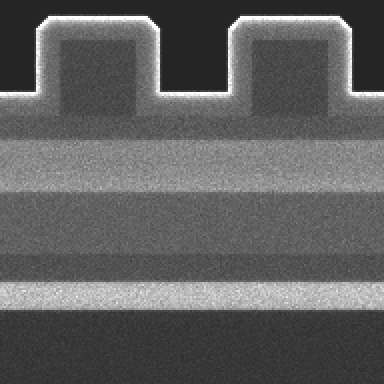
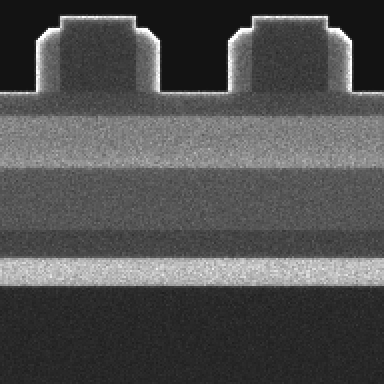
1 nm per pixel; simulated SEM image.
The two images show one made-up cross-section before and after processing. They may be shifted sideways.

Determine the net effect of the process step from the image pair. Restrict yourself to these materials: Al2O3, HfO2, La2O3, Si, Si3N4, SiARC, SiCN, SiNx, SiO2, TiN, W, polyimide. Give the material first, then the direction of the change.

Al2O3: removed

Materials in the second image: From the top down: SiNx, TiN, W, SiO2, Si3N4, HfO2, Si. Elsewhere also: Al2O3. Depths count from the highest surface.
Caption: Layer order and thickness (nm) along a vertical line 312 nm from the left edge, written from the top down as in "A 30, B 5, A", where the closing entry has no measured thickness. SiNx 76, TiN 24, W 52, SiO2 62, Si3N4 28, HfO2 28, Si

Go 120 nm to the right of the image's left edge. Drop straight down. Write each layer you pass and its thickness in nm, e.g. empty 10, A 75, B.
SiNx 76, TiN 24, W 52, SiO2 62, Si3N4 28, HfO2 28, Si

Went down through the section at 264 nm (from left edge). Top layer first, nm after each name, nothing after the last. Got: SiNx 76, TiN 24, W 52, SiO2 62, Si3N4 28, HfO2 28, Si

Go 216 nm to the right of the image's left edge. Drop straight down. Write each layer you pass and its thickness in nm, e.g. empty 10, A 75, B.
empty 76, TiN 24, W 52, SiO2 62, Si3N4 28, HfO2 28, Si